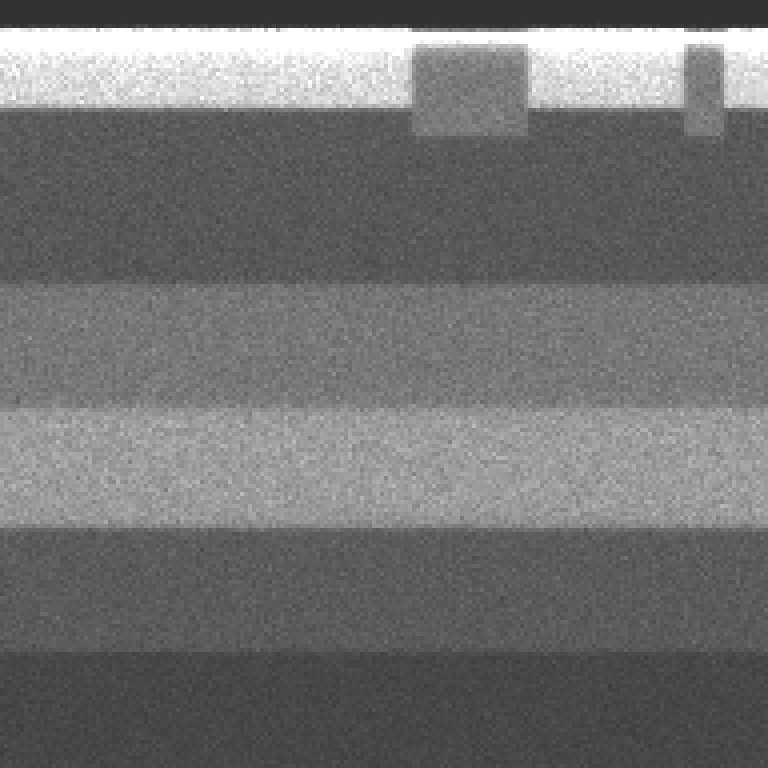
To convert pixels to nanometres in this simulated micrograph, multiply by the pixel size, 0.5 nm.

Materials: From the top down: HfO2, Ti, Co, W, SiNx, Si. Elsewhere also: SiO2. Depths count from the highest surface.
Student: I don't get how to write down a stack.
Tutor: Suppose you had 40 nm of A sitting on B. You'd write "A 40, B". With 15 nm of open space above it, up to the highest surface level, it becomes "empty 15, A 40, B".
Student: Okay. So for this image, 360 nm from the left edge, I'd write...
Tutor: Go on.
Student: SiO2 52, Ti 74, Co 62, W 60, SiNx 62, Si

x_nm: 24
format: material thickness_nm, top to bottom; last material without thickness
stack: HfO2 38, Ti 88, Co 62, W 60, SiNx 62, Si